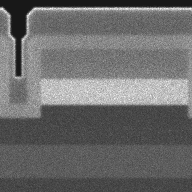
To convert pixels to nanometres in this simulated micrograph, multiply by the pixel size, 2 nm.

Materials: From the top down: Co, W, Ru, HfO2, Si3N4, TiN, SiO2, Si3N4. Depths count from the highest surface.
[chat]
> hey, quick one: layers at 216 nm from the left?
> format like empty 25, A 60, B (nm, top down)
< Co 54, W 28, Ru 60, HfO2 52, Si3N4 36, TiN 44, SiO2 66, Si3N4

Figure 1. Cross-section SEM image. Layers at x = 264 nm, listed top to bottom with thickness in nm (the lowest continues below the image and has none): Co 54, W 28, Ru 60, HfO2 52, Si3N4 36, TiN 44, SiO2 66, Si3N4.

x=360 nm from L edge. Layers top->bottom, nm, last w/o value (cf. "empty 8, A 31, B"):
Co 54, W 28, Ru 60, HfO2 52, Si3N4 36, TiN 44, SiO2 66, Si3N4